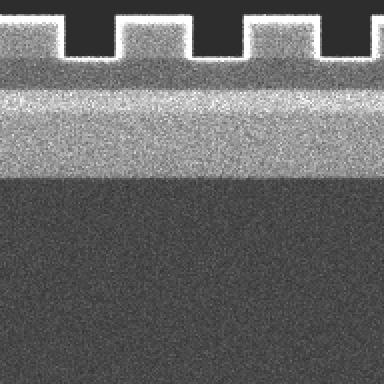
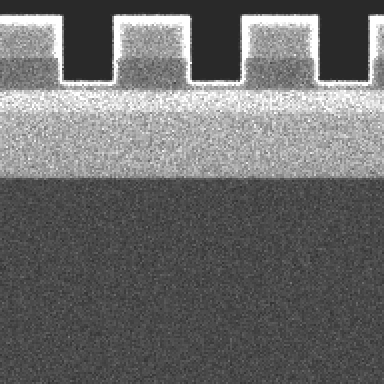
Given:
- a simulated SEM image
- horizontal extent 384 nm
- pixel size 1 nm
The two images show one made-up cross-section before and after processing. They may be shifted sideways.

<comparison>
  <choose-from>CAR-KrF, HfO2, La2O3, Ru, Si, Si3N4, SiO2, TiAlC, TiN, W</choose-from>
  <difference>TiN removed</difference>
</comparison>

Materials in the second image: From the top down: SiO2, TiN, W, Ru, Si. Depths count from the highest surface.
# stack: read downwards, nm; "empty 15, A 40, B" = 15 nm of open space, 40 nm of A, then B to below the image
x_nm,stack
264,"SiO2 42, TiN 32, W 22, Ru 66, Si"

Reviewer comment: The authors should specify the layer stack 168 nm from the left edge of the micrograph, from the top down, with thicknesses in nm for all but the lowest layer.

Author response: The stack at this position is SiO2 42, TiN 32, W 22, Ru 66, Si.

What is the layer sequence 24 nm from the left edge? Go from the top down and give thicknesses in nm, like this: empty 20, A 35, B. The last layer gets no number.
SiO2 42, TiN 32, W 22, Ru 66, Si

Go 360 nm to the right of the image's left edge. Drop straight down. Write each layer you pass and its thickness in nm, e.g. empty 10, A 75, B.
empty 66, TiN 8, W 22, Ru 66, Si